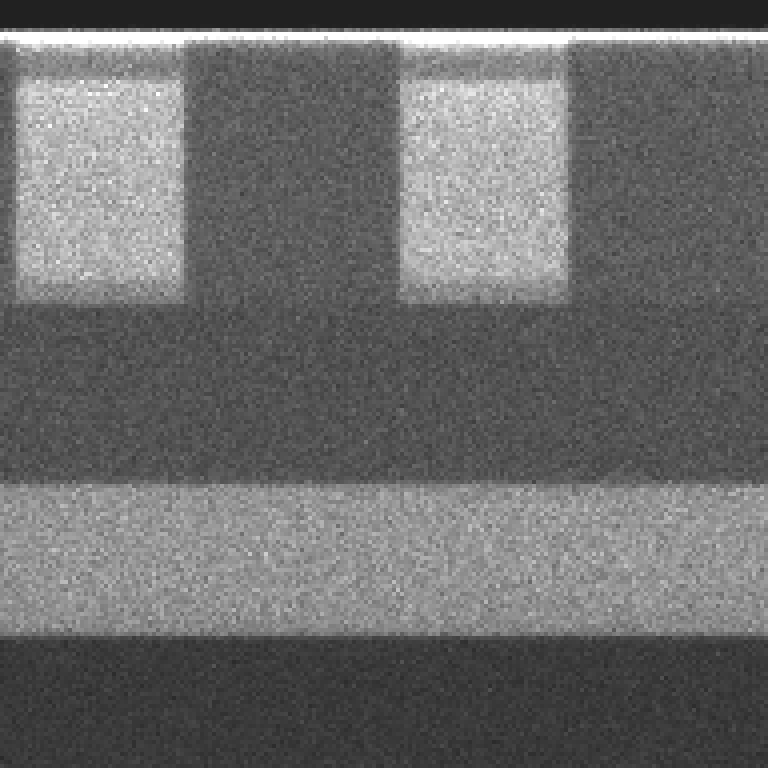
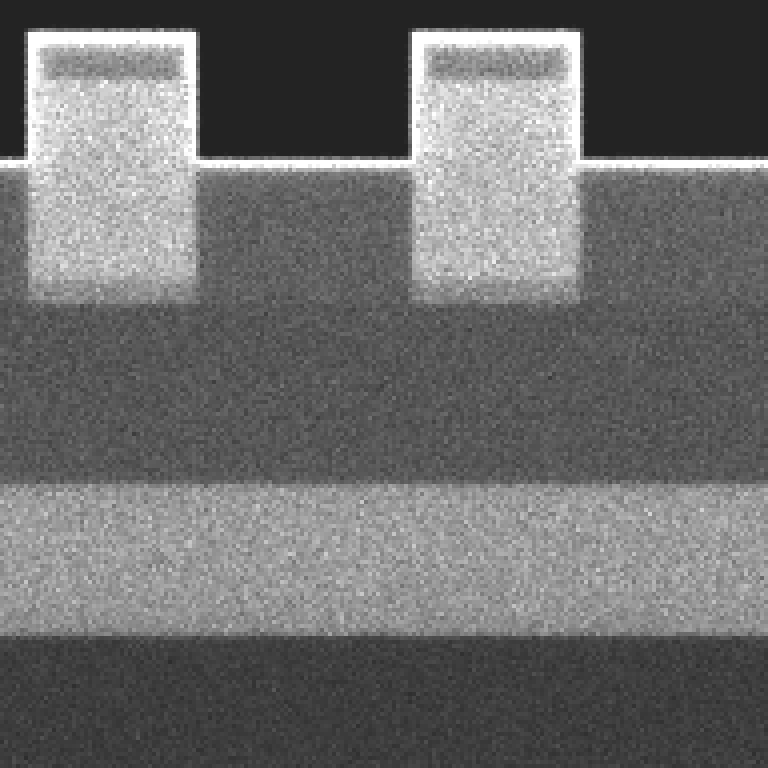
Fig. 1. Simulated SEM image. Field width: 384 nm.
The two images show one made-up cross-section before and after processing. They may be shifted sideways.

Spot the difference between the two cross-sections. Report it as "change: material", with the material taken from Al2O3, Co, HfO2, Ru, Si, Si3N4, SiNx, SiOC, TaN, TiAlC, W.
removed: Si3N4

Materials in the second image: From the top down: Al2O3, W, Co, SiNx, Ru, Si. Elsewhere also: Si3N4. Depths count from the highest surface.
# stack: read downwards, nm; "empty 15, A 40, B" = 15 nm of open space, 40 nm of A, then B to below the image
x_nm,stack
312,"empty 64, Si3N4 72, SiNx 90, Ru 76, Si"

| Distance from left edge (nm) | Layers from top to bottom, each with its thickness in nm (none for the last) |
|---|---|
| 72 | Al2O3 24, W 100, Co 12, SiNx 90, Ru 76, Si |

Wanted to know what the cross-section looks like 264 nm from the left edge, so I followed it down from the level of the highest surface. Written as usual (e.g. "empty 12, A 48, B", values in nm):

Al2O3 24, W 100, Co 12, SiNx 90, Ru 76, Si